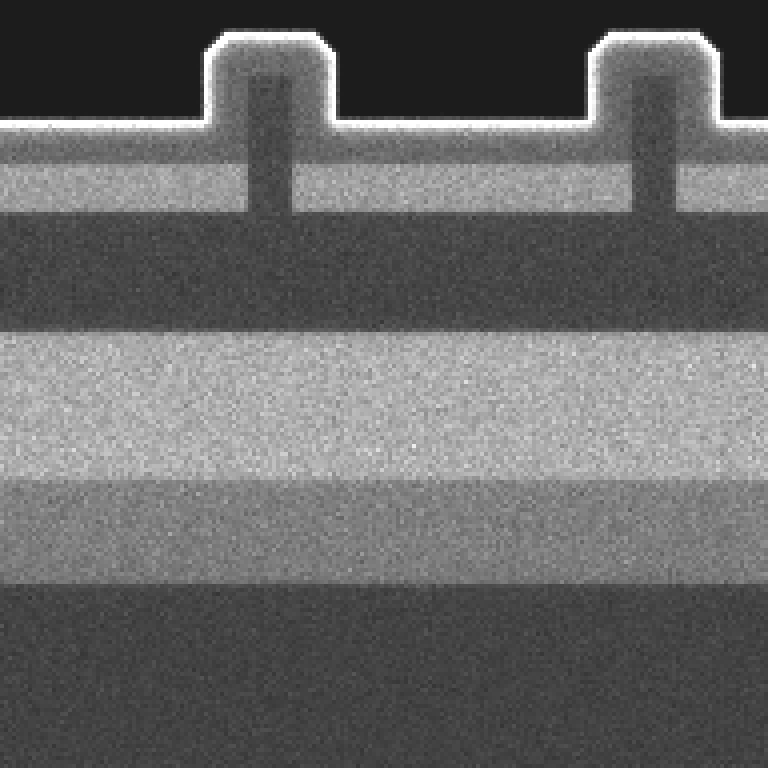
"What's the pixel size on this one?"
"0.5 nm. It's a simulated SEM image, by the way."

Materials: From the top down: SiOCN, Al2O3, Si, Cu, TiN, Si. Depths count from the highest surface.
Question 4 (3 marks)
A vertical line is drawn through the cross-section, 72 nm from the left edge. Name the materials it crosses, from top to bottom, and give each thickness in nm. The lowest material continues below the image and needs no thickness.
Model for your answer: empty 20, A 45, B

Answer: empty 44, SiOCN 22, Al2O3 24, Si 60, Cu 74, TiN 52, Si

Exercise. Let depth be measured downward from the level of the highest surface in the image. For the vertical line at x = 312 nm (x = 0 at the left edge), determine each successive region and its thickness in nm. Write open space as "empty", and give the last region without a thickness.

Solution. SiOCN 66, Al2O3 24, Si 60, Cu 74, TiN 52, Si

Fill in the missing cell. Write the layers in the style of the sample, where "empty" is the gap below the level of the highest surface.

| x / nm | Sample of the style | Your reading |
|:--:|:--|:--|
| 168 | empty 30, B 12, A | empty 44, SiOCN 22, Al2O3 24, Si 60, Cu 74, TiN 52, Si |